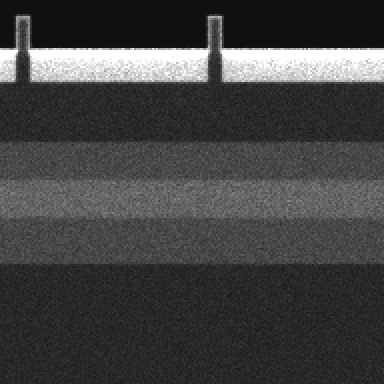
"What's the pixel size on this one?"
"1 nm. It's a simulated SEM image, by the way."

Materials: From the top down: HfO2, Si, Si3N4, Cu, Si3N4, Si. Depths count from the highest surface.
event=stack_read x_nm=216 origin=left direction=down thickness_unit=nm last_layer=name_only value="Si 126, Si3N4 38, Cu 38, Si3N4 46, Si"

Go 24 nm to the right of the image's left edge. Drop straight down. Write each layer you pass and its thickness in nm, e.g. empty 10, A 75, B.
Si 126, Si3N4 38, Cu 38, Si3N4 46, Si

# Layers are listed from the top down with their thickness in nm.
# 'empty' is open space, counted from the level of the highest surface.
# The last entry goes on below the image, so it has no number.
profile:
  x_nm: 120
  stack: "empty 34, HfO2 32, Si 60, Si3N4 38, Cu 38, Si3N4 46, Si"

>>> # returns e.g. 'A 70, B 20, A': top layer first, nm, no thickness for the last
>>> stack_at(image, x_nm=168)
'empty 34, HfO2 32, Si 60, Si3N4 38, Cu 38, Si3N4 46, Si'